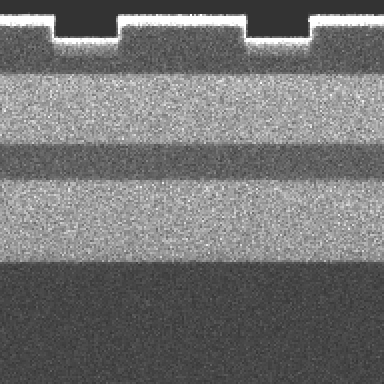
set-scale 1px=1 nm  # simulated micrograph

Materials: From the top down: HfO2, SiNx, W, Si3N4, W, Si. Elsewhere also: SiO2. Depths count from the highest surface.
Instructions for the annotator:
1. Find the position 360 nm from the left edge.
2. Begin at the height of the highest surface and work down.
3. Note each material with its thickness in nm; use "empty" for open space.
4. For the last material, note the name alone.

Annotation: HfO2 10, SiNx 48, W 70, Si3N4 36, W 82, Si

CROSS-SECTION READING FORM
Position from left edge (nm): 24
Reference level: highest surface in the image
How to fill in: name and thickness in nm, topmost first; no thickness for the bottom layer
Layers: HfO2 10, SiNx 48, W 70, Si3N4 36, W 82, Si